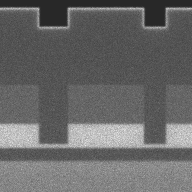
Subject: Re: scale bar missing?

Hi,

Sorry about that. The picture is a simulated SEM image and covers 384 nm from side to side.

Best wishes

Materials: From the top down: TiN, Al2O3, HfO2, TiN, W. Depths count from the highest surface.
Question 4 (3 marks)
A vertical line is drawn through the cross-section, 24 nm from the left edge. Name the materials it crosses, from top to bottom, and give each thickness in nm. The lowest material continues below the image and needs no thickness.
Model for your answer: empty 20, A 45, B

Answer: TiN 154, Al2O3 78, HfO2 48, TiN 26, W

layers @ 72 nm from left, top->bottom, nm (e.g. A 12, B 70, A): TiN 154, Al2O3 78, HfO2 48, TiN 26, W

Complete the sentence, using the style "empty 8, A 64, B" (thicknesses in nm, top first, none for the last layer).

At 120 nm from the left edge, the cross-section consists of empty 38, TiN 234, HfO2 8, TiN 26, W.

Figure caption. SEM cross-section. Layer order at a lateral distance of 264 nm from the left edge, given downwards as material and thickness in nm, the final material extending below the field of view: TiN 154, Al2O3 78, HfO2 48, TiN 26, W